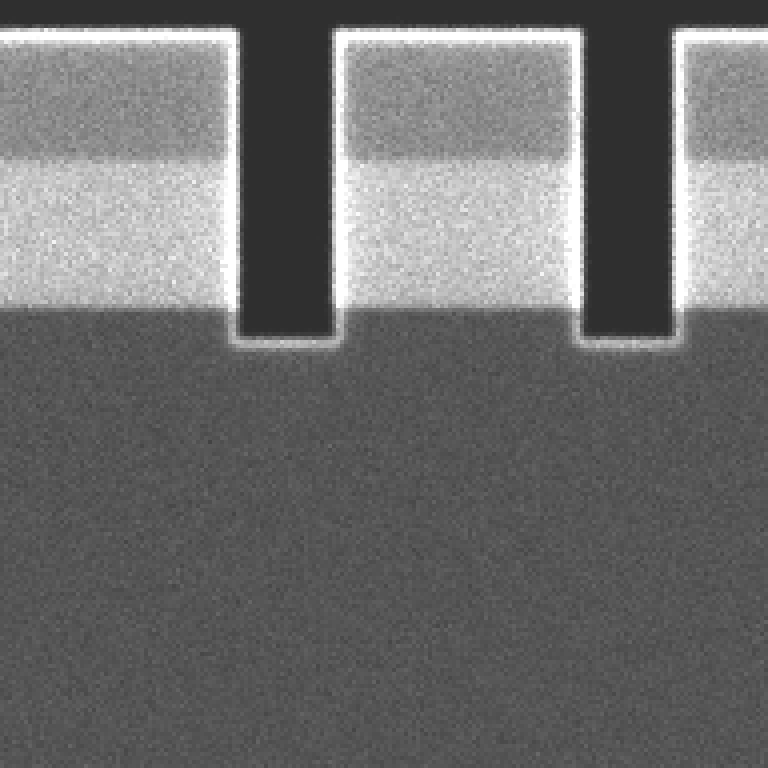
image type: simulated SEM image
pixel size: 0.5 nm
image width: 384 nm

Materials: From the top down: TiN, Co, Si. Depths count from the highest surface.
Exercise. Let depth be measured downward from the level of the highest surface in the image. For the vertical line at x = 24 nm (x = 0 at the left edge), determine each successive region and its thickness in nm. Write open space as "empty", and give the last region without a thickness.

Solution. TiN 64, Co 74, Si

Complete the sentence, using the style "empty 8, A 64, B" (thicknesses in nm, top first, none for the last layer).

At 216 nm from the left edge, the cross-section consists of TiN 64, Co 74, Si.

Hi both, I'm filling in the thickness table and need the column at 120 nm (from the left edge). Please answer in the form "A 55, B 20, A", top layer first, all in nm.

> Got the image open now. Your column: empty 154, Si